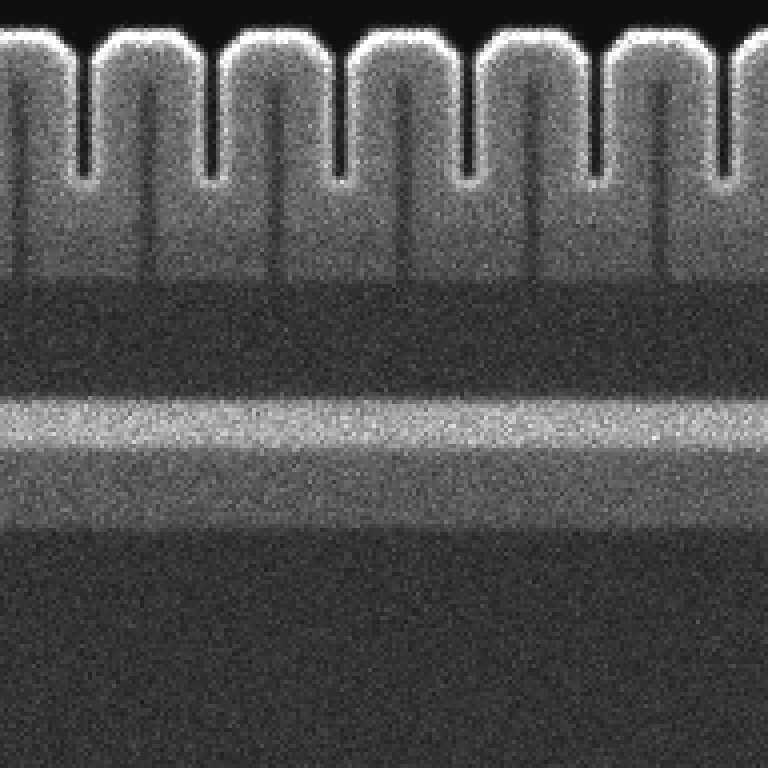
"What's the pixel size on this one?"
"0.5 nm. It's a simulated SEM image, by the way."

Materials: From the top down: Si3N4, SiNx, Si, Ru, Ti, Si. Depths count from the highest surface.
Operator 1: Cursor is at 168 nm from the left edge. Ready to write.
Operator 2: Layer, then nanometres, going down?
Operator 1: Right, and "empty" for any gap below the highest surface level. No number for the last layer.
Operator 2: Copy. empty 74, Si3N4 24, SiNx 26, Si 60, Ru 24, Ti 40, Si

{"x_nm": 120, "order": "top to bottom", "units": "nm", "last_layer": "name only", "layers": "empty 2, Si3N4 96, SiNx 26, Si 60, Ru 24, Ti 40, Si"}